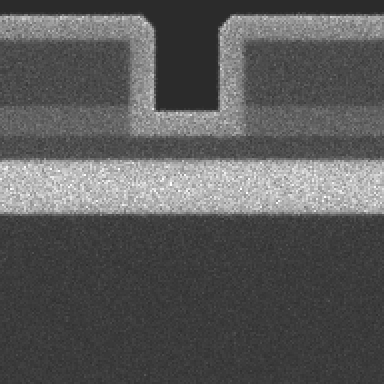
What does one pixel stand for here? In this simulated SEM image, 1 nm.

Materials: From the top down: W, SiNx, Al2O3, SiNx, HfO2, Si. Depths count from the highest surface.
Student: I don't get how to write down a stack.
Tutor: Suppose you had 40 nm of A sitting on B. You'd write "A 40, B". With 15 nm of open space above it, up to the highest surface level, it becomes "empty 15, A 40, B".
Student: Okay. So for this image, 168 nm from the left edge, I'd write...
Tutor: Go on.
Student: empty 96, W 24, SiNx 24, HfO2 54, Si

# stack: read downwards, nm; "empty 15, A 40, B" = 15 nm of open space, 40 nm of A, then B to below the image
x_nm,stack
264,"W 24, SiNx 66, Al2O3 30, SiNx 24, HfO2 54, Si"